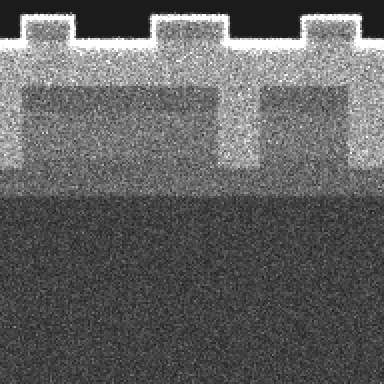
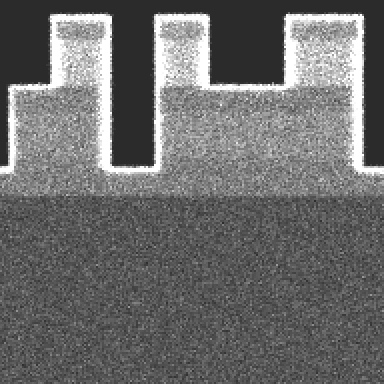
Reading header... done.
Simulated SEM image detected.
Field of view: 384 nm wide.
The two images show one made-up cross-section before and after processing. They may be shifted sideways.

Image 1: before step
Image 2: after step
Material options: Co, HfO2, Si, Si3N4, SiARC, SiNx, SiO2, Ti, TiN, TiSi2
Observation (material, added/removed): SiO2, removed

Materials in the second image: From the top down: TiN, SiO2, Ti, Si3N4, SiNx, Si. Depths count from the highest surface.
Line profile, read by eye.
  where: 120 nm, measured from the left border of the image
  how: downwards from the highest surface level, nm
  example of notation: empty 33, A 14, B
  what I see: empty 152, SiNx 28, Si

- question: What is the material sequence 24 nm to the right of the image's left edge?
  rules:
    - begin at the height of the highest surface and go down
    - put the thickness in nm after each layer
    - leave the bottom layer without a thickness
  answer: empty 70, Ti 26, Si3N4 46, SiNx 38, Si